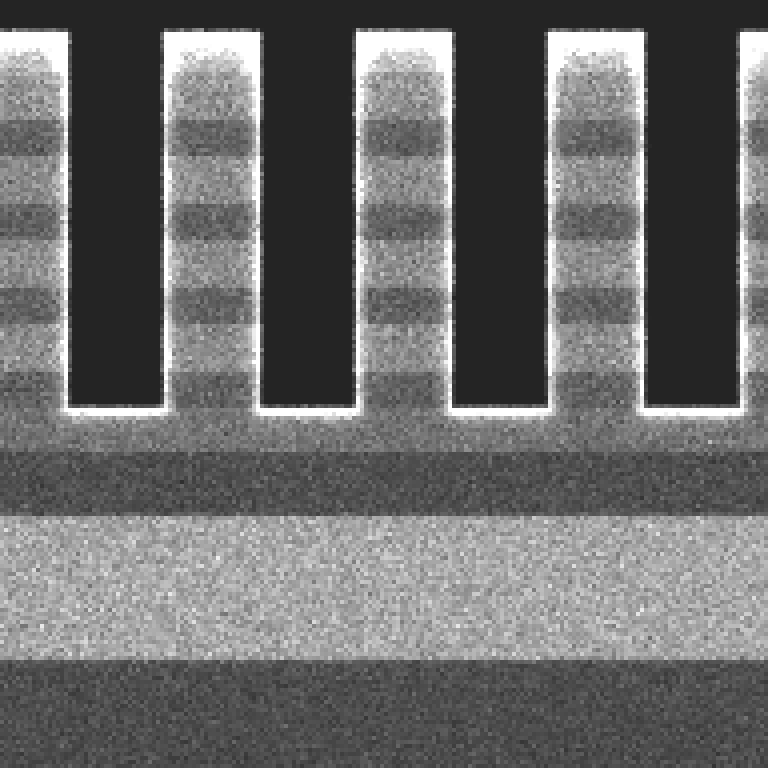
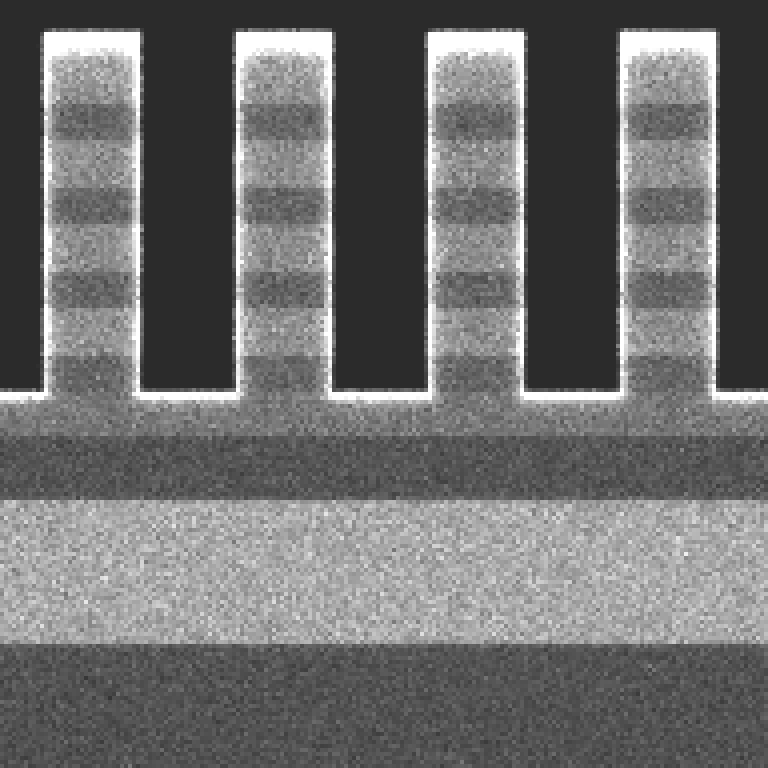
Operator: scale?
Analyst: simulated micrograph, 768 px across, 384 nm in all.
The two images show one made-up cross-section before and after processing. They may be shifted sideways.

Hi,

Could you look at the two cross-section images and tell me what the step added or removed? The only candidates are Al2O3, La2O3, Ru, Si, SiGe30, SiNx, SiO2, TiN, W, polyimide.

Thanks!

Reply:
removed Al2O3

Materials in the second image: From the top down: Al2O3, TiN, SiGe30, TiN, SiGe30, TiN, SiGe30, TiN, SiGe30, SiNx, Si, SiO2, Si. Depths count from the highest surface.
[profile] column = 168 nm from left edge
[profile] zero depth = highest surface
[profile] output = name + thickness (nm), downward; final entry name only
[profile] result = empty 180, SiNx 22, Si 32, SiO2 72, Si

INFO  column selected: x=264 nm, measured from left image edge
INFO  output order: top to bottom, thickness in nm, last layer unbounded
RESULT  empty 180, SiNx 22, Si 32, SiO2 72, Si